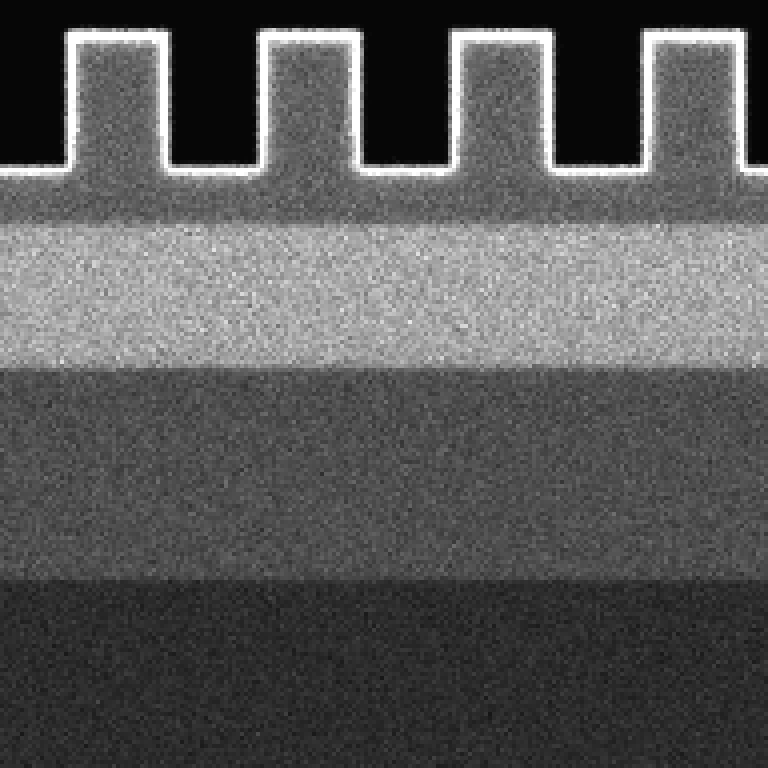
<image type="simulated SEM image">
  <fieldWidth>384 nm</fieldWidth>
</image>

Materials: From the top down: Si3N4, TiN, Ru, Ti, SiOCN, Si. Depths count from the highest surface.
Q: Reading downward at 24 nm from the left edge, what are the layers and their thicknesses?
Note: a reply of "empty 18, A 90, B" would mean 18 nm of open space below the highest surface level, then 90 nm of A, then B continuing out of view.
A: empty 68, TiN 28, Ru 72, Ti 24, SiOCN 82, Si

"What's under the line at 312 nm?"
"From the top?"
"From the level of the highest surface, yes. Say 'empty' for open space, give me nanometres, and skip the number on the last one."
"empty 68, TiN 28, Ru 72, Ti 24, SiOCN 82, Si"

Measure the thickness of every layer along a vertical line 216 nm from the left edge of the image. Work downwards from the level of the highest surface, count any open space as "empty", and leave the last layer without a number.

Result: empty 68, TiN 28, Ru 72, Ti 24, SiOCN 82, Si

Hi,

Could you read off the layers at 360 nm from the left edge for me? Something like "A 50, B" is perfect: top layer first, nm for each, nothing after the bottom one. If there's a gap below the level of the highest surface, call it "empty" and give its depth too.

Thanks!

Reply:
Si3N4 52, TiN 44, Ru 72, Ti 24, SiOCN 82, Si